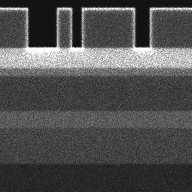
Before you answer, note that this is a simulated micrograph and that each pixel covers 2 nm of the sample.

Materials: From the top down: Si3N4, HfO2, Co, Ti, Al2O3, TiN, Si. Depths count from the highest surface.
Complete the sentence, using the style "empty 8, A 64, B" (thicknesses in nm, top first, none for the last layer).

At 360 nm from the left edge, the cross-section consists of Si3N4 80, HfO2 40, Co 16, Ti 70, Al2O3 34, TiN 72, Si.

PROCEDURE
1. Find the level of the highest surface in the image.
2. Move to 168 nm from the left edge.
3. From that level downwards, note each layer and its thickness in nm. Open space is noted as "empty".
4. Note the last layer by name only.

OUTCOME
Si3N4 80, HfO2 40, Co 16, Ti 70, Al2O3 34, TiN 72, Si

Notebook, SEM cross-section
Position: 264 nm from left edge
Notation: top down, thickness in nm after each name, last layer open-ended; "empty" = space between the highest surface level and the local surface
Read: Si3N4 80, HfO2 40, Co 16, Ti 70, Al2O3 34, TiN 72, Si